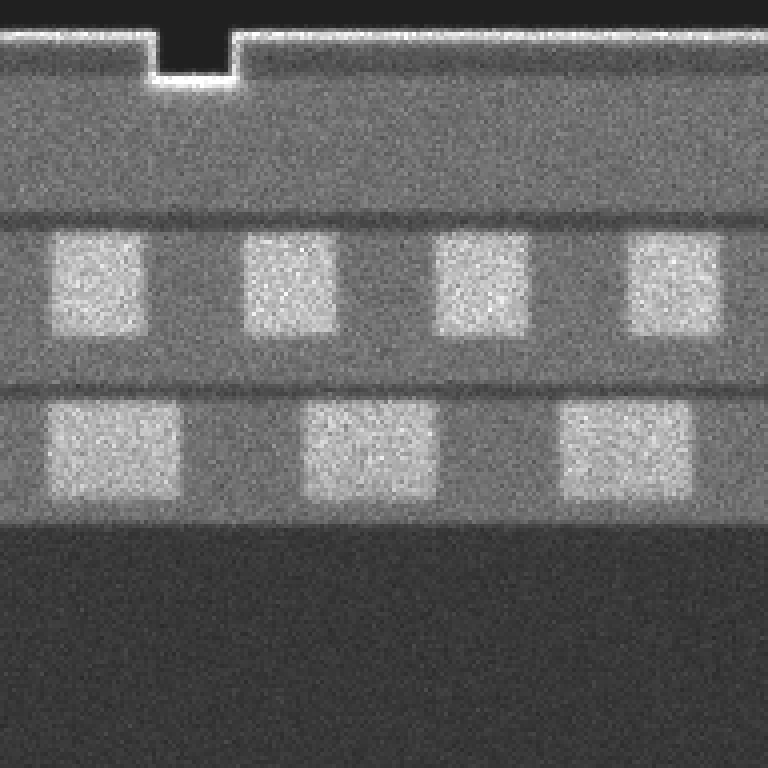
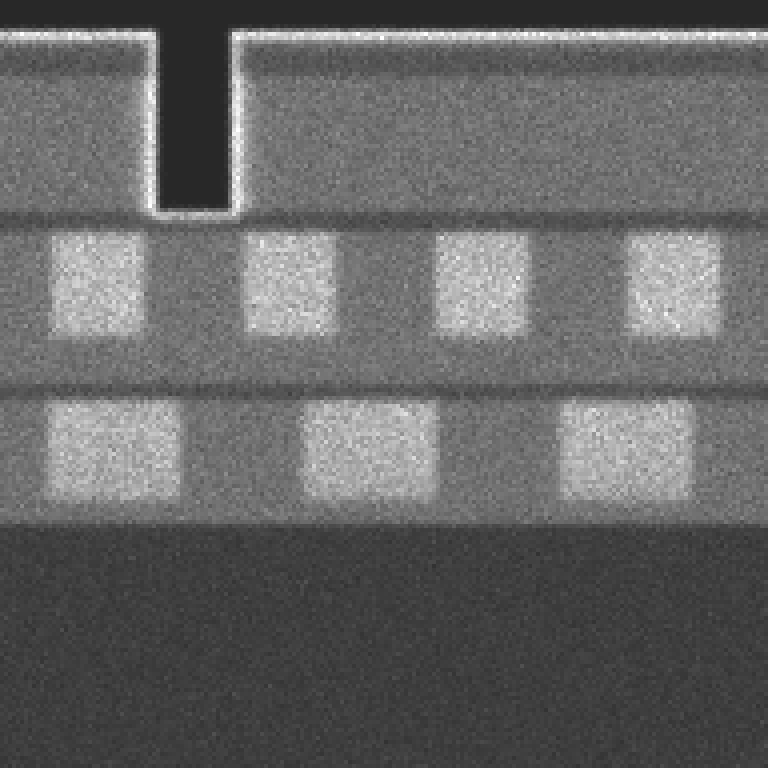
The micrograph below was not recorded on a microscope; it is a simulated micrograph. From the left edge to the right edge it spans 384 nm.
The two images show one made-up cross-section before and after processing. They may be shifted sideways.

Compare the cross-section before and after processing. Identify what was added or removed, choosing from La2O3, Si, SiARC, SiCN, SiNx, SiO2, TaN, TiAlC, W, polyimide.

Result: SiO2 removed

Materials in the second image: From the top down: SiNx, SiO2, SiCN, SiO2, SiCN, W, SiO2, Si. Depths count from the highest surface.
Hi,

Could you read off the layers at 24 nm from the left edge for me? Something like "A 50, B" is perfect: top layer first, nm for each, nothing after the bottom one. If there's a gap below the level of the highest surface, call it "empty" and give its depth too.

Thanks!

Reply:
SiNx 22, SiO2 68, SiCN 10, SiO2 76, SiCN 8, W 50, SiO2 12, Si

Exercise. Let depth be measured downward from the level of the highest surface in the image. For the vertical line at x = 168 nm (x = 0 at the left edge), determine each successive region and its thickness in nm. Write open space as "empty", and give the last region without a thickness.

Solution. SiNx 22, SiO2 68, SiCN 10, SiO2 76, SiCN 8, W 50, SiO2 12, Si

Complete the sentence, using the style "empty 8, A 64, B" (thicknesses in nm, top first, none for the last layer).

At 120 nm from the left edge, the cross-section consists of SiNx 22, SiO2 68, SiCN 10, SiO2 76, SiCN 8, SiO2 62, Si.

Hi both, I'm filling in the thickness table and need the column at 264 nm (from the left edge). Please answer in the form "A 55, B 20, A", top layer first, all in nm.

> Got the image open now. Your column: SiNx 22, SiO2 68, SiCN 10, SiO2 76, SiCN 8, SiO2 62, Si